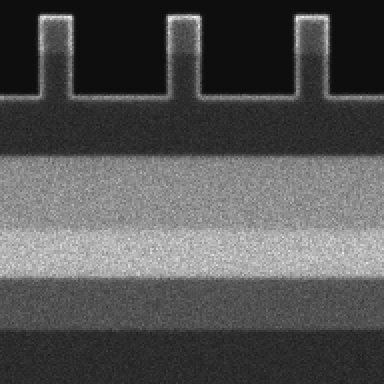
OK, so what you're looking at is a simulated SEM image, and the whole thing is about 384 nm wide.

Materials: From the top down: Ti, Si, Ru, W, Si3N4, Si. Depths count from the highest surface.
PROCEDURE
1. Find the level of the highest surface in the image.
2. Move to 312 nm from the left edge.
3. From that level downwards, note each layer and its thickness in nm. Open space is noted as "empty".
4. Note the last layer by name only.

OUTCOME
Ti 38, Si 102, Ru 74, W 48, Si3N4 52, Si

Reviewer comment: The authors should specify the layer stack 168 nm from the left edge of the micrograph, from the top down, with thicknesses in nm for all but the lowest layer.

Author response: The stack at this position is Ti 38, Si 102, Ru 74, W 48, Si3N4 52, Si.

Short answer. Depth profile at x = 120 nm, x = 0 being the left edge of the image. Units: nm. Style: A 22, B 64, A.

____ empty 80, Si 60, Ru 74, W 48, Si3N4 52, Si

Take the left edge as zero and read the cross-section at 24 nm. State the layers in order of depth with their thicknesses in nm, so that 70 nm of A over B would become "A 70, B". empty 80, Si 60, Ru 74, W 48, Si3N4 52, Si